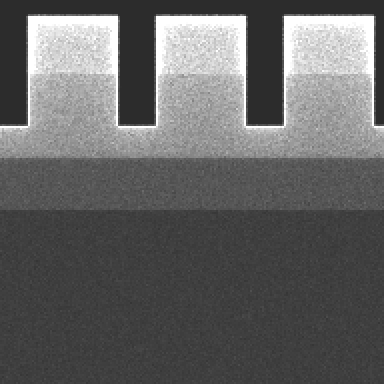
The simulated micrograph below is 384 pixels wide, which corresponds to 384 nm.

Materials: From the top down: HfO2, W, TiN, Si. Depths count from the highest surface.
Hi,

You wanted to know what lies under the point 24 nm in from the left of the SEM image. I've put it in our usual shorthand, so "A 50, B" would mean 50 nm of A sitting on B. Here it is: empty 110, W 32, TiN 52, Si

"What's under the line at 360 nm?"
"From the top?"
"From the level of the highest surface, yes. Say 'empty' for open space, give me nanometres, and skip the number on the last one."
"HfO2 58, W 84, TiN 52, Si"